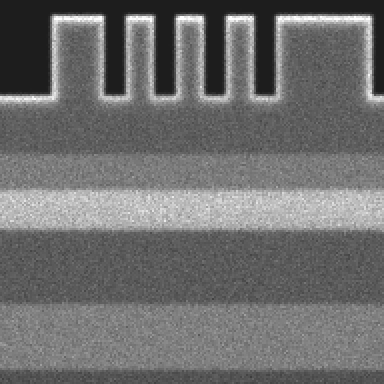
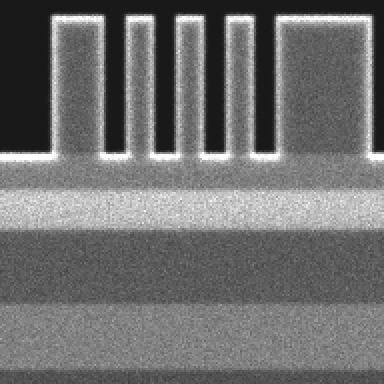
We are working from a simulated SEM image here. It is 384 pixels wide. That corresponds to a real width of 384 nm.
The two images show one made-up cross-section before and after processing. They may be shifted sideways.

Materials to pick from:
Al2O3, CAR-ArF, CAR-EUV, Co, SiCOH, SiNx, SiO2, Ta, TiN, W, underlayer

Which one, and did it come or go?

underlayer - removed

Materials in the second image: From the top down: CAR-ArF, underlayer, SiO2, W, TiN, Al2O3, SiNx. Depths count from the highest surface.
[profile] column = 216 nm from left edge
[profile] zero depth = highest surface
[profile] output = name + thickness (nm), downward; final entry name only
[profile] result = empty 138, SiO2 36, W 40, TiN 74, Al2O3 66, SiNx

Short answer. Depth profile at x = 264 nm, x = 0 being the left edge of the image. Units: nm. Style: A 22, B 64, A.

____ empty 138, SiO2 36, W 40, TiN 74, Al2O3 66, SiNx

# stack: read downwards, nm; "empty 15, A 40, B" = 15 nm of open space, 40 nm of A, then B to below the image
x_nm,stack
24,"empty 138, SiO2 36, W 40, TiN 74, Al2O3 66, SiNx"